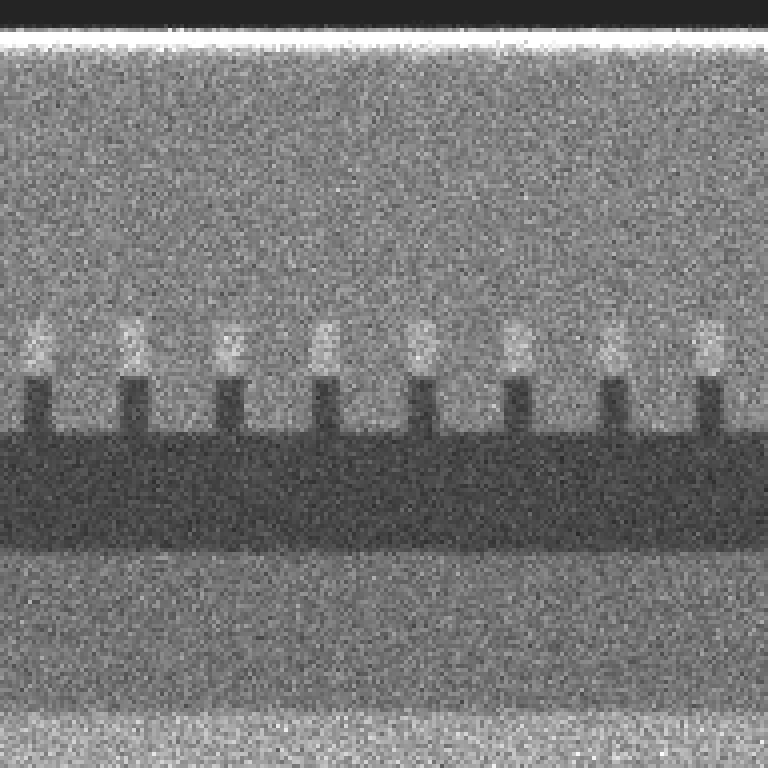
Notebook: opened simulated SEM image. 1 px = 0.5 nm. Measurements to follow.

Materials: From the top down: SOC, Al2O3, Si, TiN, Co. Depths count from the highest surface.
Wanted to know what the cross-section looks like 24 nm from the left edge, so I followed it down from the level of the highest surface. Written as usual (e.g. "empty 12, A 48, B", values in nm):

SOC 144, Al2O3 28, Si 88, TiN 80, Co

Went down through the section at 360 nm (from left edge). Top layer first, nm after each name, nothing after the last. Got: SOC 144, Al2O3 28, Si 88, TiN 80, Co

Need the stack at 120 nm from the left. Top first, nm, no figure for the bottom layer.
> SOC 144, Al2O3 28, Si 88, TiN 80, Co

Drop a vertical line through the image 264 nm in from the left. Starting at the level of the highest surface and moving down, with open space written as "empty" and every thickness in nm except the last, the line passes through SOC 144, Al2O3 28, Si 88, TiN 80, Co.